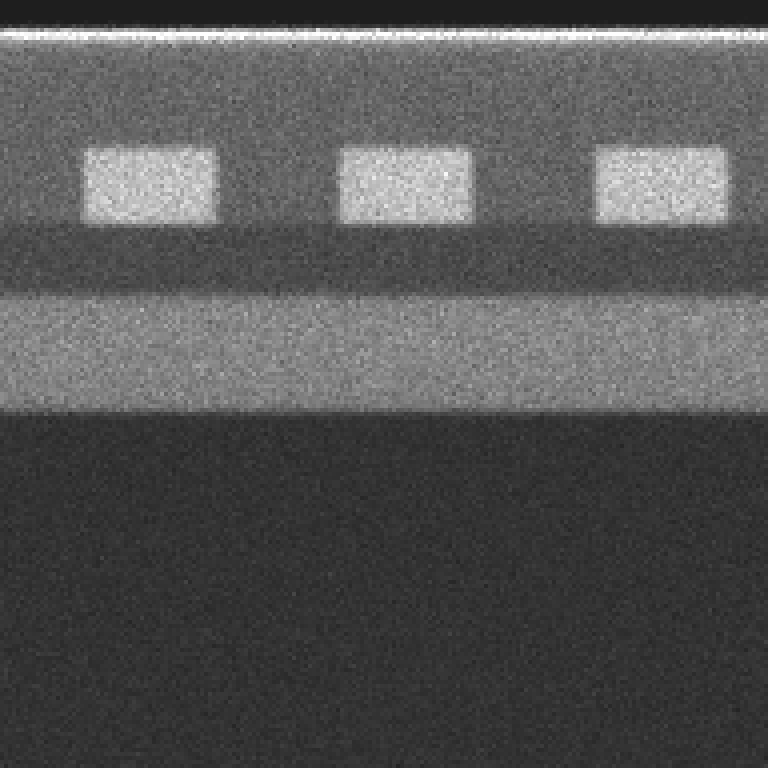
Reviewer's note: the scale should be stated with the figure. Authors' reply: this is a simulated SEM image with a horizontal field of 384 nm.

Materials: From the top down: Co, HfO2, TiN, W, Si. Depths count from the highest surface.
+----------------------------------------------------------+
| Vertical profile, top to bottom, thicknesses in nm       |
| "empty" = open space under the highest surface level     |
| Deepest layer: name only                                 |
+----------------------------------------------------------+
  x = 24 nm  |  Co 96, TiN 36, W 58, Si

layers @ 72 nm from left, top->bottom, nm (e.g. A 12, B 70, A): Co 58, HfO2 38, TiN 36, W 58, Si